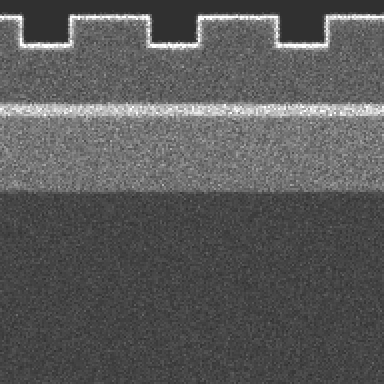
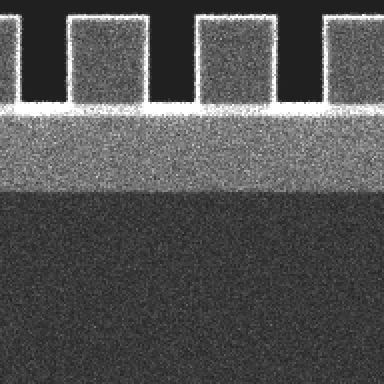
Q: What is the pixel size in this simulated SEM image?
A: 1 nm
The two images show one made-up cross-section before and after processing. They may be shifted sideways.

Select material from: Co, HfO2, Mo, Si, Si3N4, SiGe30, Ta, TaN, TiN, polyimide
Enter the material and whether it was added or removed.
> Si3N4 / removed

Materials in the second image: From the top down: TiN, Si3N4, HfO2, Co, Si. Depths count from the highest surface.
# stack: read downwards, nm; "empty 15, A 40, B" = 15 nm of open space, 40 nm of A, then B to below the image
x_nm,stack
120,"TiN 28, Si3N4 60, HfO2 12, Co 76, Si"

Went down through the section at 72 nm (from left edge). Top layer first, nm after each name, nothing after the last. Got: TiN 28, Si3N4 60, HfO2 12, Co 76, Si